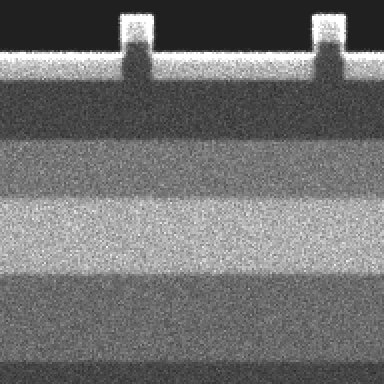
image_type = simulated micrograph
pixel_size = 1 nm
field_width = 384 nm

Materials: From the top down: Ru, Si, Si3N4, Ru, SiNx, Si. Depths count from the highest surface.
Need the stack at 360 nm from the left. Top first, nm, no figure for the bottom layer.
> empty 38, Ru 26, Si 60, Si3N4 58, Ru 76, SiNx 88, Si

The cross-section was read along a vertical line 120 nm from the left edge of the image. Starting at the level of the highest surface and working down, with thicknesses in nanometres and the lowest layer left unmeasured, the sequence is empty 38, Ru 26, Si 60, Si3N4 58, Ru 76, SiNx 88, Si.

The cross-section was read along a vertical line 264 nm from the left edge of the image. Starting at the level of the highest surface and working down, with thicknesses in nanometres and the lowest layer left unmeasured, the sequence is empty 38, Ru 26, Si 60, Si3N4 58, Ru 76, SiNx 88, Si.